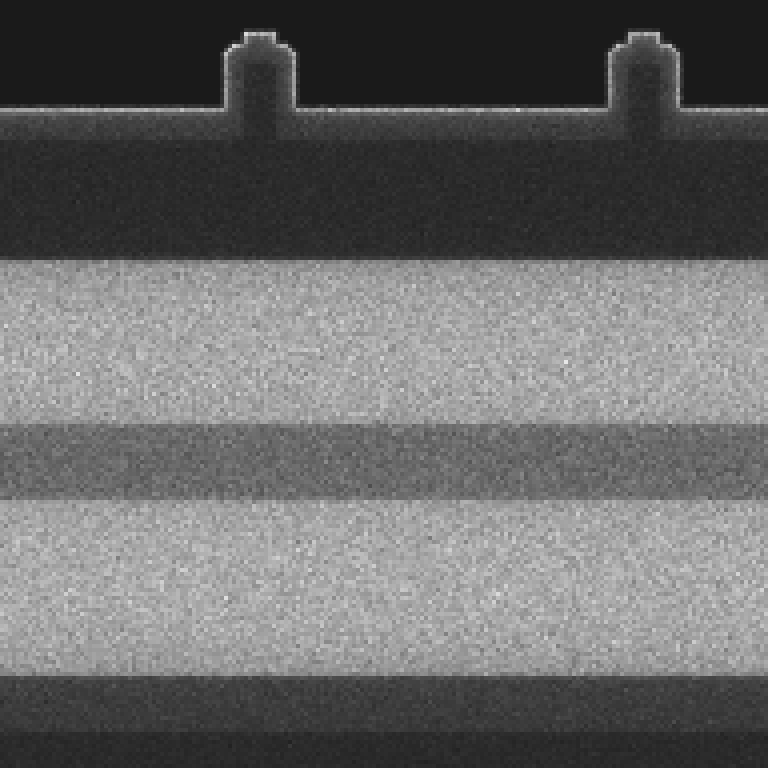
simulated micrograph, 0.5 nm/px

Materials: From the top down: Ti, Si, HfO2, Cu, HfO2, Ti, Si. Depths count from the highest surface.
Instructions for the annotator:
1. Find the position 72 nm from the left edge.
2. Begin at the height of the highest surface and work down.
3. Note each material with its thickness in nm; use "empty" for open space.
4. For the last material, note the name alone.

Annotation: empty 38, Ti 16, Si 60, HfO2 82, Cu 38, HfO2 88, Ti 28, Si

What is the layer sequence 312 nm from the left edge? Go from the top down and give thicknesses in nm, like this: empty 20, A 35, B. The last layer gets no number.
empty 6, Ti 48, Si 60, HfO2 82, Cu 38, HfO2 88, Ti 28, Si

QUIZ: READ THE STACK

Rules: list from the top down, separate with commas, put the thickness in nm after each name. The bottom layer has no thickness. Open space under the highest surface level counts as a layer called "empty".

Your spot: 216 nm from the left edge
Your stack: empty 38, Ti 16, Si 60, HfO2 82, Cu 38, HfO2 88, Ti 28, Si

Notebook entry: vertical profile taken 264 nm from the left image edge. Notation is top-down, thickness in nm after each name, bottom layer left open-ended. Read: empty 38, Ti 16, Si 60, HfO2 82, Cu 38, HfO2 88, Ti 28, Si